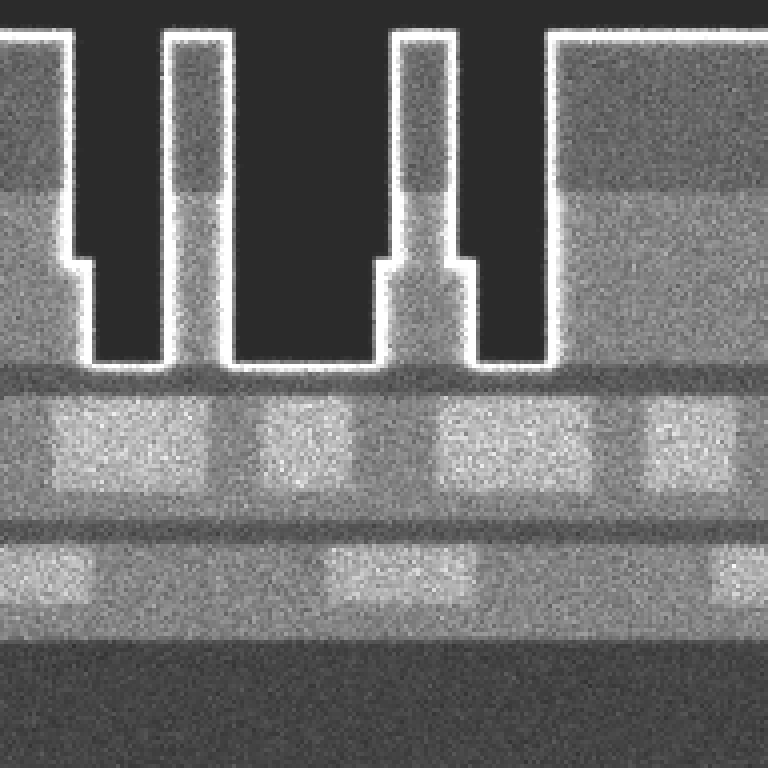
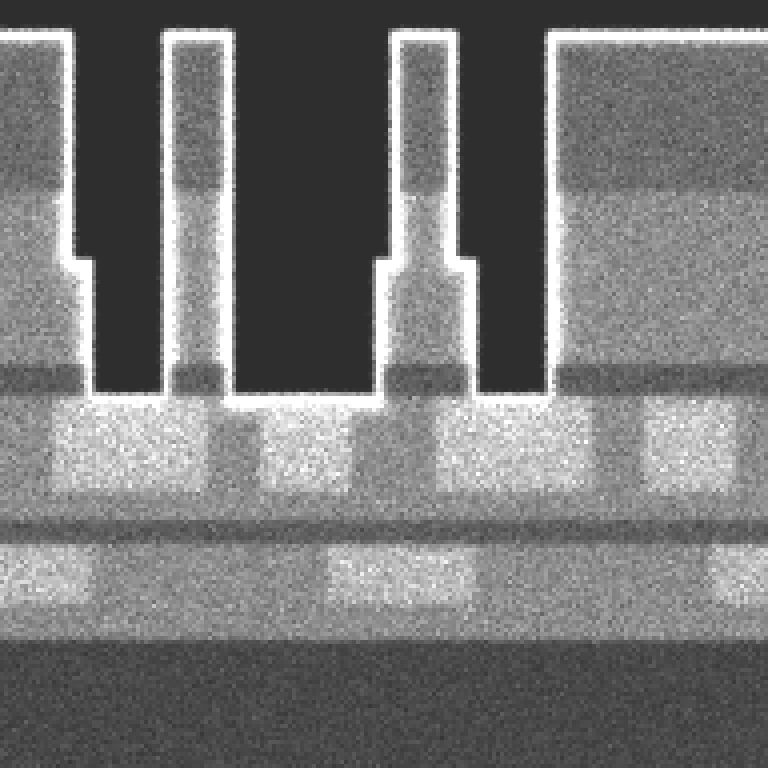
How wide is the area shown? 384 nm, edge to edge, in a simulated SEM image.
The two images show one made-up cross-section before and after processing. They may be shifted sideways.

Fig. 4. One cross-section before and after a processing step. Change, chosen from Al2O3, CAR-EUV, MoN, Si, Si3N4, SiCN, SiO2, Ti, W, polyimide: SiCN removed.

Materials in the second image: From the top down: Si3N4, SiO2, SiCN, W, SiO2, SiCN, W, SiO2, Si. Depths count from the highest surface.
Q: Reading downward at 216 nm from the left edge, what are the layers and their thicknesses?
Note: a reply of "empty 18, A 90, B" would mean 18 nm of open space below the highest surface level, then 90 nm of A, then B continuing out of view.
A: Si3N4 80, SiO2 86, SiCN 16, SiO2 62, SiCN 12, W 30, SiO2 18, Si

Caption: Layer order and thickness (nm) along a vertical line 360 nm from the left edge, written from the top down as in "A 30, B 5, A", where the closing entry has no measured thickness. Si3N4 80, SiO2 86, SiCN 16, W 48, SiO2 14, SiCN 12, W 30, SiO2 18, Si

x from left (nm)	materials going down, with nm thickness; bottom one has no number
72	empty 182, W 48, SiO2 14, SiCN 12, SiO2 48, Si